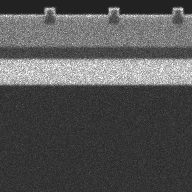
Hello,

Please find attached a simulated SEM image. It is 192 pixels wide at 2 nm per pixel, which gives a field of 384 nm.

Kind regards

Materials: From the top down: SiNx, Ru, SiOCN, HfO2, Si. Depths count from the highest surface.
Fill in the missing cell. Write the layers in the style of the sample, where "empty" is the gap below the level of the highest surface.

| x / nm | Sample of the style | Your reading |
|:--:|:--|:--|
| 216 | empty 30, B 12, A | empty 14, Ru 64, SiOCN 24, HfO2 52, Si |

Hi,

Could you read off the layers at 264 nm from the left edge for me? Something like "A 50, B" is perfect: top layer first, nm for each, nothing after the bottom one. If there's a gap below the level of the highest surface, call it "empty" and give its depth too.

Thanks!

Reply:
empty 14, Ru 64, SiOCN 24, HfO2 52, Si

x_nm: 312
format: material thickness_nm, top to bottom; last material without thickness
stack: empty 14, Ru 64, SiOCN 24, HfO2 52, Si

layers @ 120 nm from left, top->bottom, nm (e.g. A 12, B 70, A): empty 14, Ru 64, SiOCN 24, HfO2 52, Si